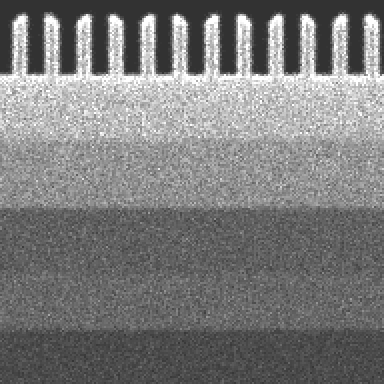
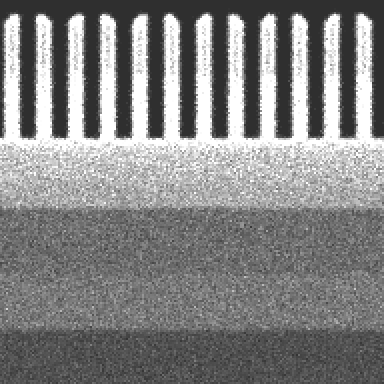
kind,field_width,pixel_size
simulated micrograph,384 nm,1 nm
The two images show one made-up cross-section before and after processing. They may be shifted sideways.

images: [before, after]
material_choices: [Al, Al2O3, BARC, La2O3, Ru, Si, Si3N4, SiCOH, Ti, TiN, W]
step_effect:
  removed: W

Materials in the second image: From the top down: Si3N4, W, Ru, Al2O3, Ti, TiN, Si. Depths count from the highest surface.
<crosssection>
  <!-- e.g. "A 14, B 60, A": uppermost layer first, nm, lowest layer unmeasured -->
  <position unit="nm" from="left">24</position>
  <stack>empty 124, Ru 44, Al2O3 24, Ti 66, TiN 56, Si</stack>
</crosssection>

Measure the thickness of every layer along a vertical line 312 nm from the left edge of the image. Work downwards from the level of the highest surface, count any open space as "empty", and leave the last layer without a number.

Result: empty 124, Ru 44, Al2O3 24, Ti 66, TiN 56, Si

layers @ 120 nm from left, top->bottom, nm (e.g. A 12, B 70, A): empty 124, Ru 44, Al2O3 24, Ti 66, TiN 56, Si